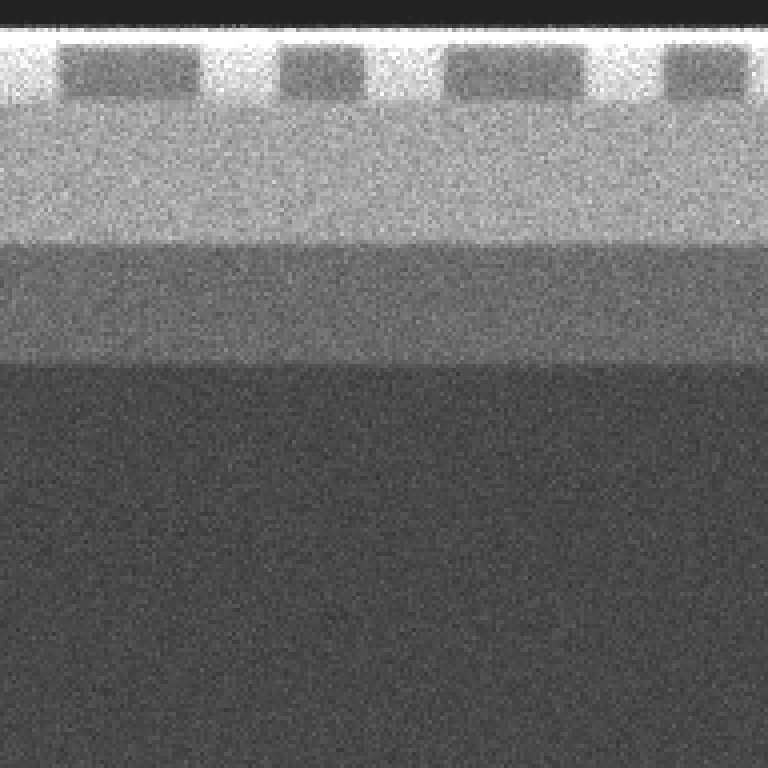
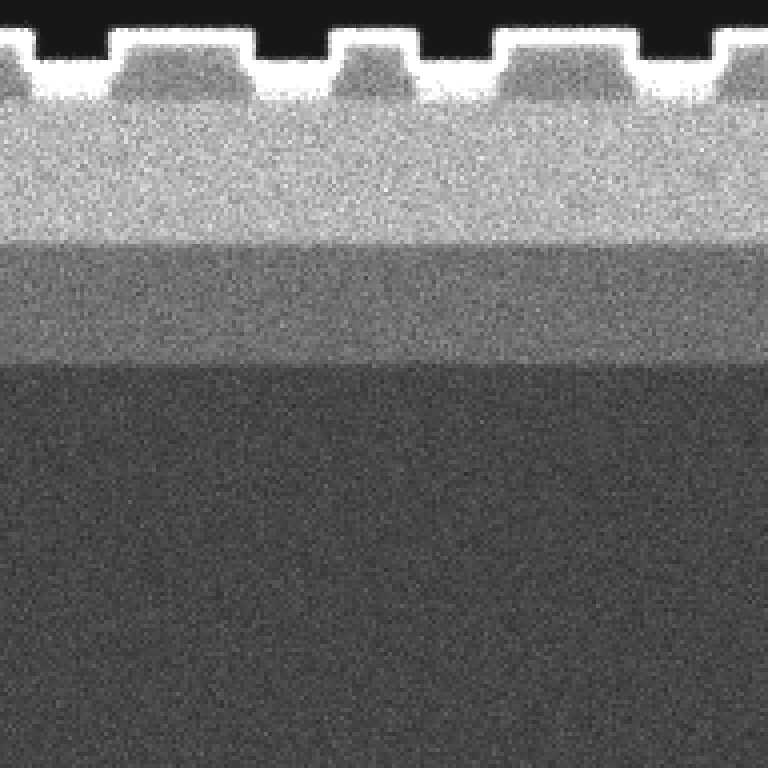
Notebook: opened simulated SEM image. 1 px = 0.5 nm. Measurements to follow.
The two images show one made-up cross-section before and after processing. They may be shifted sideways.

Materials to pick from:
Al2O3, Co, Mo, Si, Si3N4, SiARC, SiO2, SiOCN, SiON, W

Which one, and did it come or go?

Co - removed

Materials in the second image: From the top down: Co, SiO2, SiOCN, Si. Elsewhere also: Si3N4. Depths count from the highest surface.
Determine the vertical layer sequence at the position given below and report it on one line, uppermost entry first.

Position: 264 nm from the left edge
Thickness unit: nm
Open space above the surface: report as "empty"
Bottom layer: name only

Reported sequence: Si3N4 34, SiO2 72, SiOCN 60, Si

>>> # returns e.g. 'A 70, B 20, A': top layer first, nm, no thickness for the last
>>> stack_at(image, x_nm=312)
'Si3N4 34, SiO2 72, SiOCN 60, Si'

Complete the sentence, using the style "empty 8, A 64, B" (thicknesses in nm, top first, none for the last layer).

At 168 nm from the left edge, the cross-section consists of Si3N4 34, SiO2 72, SiOCN 60, Si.